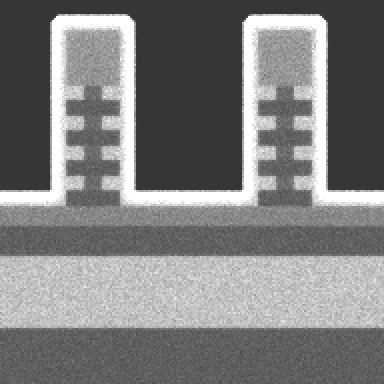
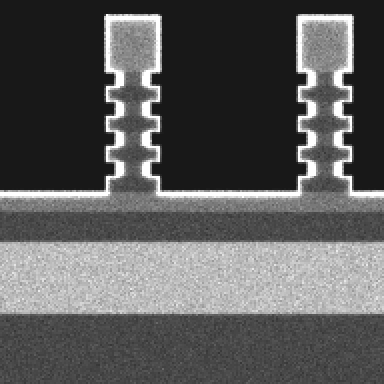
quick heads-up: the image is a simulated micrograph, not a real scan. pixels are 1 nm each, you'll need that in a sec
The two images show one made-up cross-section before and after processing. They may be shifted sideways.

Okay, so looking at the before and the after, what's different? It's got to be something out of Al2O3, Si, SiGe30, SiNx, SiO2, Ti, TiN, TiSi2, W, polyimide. Al2O3, removed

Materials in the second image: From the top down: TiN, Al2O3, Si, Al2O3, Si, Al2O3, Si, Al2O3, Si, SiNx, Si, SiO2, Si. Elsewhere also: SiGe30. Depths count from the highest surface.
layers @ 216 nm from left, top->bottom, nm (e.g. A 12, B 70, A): empty 176, SiNx 20, Si 30, SiO2 72, Si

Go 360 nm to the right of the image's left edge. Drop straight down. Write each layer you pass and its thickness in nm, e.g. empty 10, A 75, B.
empty 176, SiNx 20, Si 30, SiO2 72, Si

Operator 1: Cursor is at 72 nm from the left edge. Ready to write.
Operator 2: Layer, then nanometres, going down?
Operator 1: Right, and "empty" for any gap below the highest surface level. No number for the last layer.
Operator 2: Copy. empty 176, SiNx 20, Si 30, SiO2 72, Si